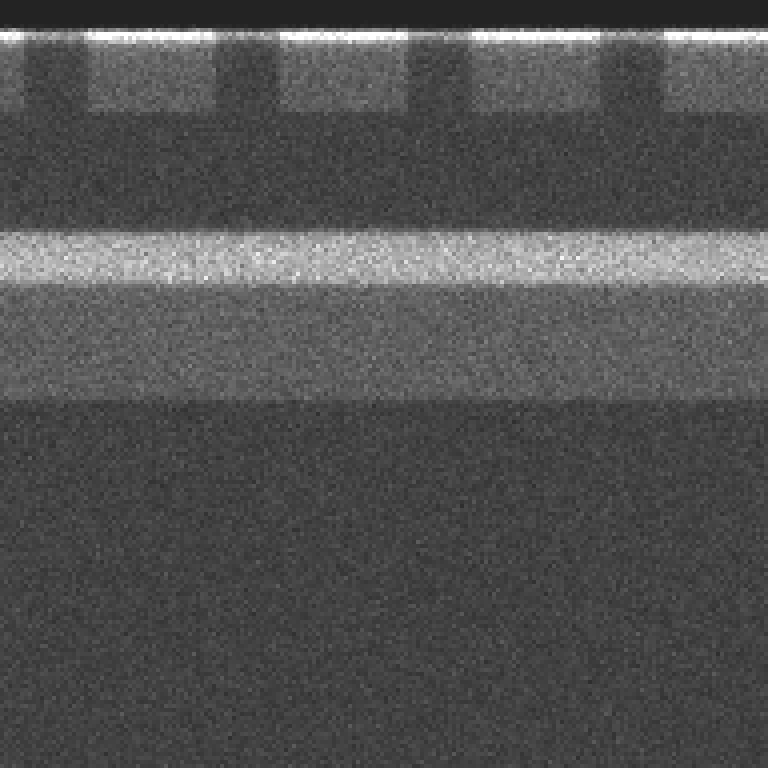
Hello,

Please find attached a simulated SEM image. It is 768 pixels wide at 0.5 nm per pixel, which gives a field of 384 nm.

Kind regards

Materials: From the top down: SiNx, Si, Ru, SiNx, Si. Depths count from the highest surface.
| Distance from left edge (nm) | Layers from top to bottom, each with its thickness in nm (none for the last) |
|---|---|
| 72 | SiNx 40, Si 60, Ru 26, SiNx 58, Si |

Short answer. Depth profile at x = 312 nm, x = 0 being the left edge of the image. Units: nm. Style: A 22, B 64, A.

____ Si 100, Ru 26, SiNx 58, Si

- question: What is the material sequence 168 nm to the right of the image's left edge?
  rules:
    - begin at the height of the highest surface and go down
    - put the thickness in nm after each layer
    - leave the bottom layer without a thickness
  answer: SiNx 40, Si 60, Ru 26, SiNx 58, Si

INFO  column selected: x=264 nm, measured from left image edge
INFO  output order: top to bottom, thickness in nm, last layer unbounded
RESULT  SiNx 40, Si 60, Ru 26, SiNx 58, Si